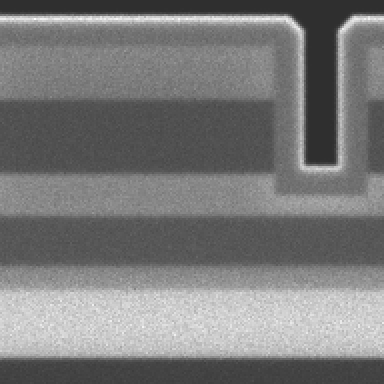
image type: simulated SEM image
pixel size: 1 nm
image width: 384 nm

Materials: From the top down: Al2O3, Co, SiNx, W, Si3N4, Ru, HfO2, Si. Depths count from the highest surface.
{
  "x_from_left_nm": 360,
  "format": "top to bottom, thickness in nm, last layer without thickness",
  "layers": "Al2O3 180, W 20, Si3N4 50, Ru 24, HfO2 68, Si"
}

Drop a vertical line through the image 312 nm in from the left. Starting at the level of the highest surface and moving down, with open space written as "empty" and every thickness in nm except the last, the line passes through empty 150, Al2O3 30, W 20, Si3N4 50, Ru 24, HfO2 68, Si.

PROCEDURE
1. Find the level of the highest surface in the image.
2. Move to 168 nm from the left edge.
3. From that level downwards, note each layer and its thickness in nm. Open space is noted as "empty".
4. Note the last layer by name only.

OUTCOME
Al2O3 30, Co 54, SiNx 74, W 42, Si3N4 50, Ru 24, HfO2 68, Si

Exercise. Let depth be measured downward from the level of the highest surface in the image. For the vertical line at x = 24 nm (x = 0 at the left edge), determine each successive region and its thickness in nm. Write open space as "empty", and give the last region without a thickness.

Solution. Al2O3 30, Co 54, SiNx 74, W 42, Si3N4 50, Ru 24, HfO2 68, Si